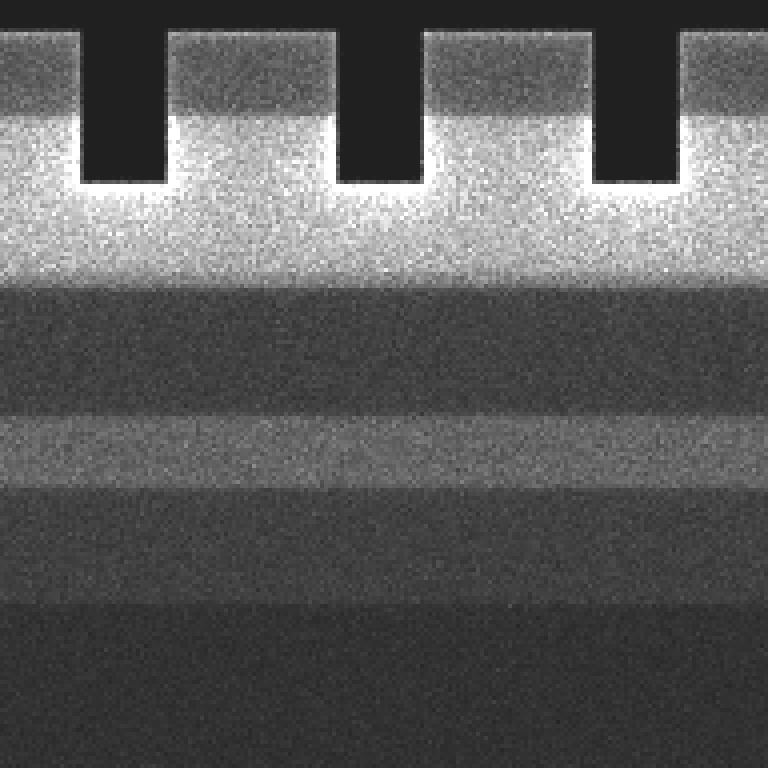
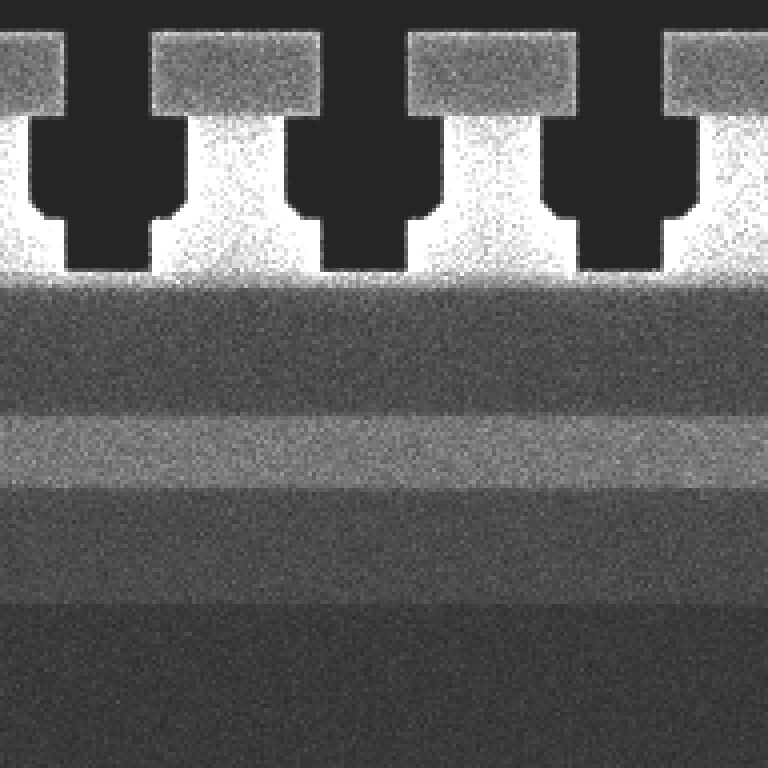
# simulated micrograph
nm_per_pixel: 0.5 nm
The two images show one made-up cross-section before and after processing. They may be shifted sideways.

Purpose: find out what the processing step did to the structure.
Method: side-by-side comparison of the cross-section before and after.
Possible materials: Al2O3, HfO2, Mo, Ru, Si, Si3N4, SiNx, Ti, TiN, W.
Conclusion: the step removed HfO2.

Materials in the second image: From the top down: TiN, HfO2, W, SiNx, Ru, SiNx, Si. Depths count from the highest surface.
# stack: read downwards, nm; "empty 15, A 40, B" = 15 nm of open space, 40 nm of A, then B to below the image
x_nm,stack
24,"TiN 42, empty 52, HfO2 26, W 8, SiNx 64, Ru 36, SiNx 58, Si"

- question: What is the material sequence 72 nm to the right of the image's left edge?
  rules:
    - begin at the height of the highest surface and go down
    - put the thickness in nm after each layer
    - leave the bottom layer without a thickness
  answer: empty 120, W 8, SiNx 64, Ru 36, SiNx 58, Si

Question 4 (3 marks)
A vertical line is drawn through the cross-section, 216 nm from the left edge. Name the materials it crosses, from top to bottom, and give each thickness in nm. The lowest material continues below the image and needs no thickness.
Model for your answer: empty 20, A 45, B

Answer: TiN 42, empty 48, HfO2 30, W 8, SiNx 64, Ru 36, SiNx 58, Si